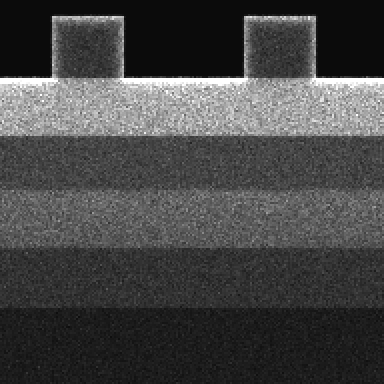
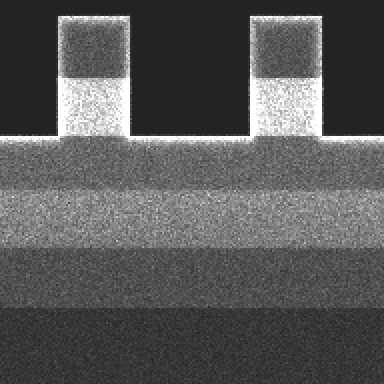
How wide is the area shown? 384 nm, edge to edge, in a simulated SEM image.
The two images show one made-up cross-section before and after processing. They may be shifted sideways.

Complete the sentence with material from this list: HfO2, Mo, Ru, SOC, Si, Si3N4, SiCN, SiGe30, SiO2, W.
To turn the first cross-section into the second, HfO2 must be removed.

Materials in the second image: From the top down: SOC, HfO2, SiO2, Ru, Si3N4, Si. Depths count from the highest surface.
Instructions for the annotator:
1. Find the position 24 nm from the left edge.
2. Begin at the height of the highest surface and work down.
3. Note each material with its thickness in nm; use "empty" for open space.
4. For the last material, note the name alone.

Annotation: empty 120, SiO2 54, Ru 58, Si3N4 60, Si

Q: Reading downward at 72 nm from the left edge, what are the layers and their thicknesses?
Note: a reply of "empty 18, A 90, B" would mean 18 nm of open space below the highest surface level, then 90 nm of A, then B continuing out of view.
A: SOC 62, HfO2 58, SiO2 54, Ru 58, Si3N4 60, Si